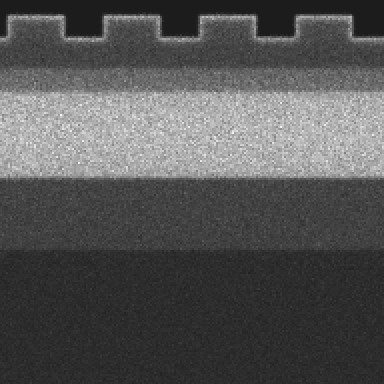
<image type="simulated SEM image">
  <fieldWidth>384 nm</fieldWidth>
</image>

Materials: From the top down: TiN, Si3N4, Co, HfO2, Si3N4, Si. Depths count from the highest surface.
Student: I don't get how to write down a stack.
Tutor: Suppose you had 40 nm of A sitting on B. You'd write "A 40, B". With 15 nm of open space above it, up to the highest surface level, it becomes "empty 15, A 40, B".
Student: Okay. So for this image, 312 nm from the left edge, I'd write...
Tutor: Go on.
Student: TiN 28, Si3N4 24, Co 24, HfO2 86, Si3N4 72, Si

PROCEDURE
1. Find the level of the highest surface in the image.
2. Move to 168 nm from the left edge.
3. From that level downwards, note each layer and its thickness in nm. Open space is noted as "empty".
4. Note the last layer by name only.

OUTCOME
empty 22, TiN 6, Si3N4 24, Co 24, HfO2 86, Si3N4 72, Si